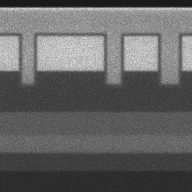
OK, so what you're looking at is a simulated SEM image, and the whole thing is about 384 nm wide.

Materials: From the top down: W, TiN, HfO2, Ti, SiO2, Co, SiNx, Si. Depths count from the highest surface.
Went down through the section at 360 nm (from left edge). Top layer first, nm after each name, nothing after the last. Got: W 50, TiN 108, Ti 50, SiO2 46, Co 36, SiNx 36, Si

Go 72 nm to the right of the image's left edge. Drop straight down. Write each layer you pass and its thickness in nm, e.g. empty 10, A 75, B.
W 50, TiN 108, Ti 50, SiO2 46, Co 36, SiNx 36, Si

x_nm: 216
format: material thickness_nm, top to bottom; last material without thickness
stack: W 152, TiN 6, Ti 50, SiO2 46, Co 36, SiNx 36, Si